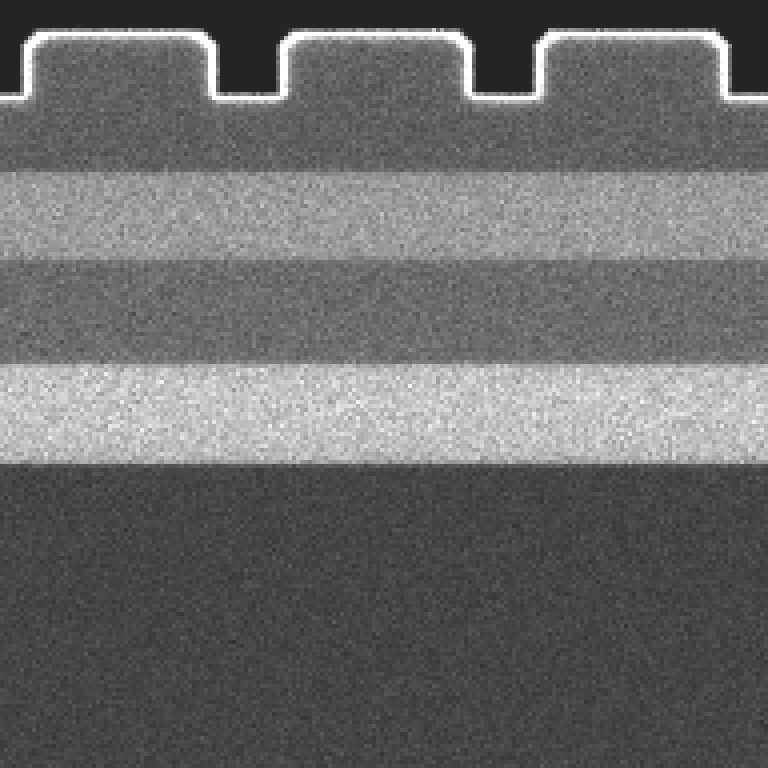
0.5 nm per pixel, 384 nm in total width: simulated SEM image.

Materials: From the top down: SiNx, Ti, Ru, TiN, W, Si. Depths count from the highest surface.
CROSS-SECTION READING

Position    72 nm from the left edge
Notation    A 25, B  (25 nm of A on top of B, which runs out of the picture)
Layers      Ti 70, Ru 44, TiN 52, W 50, Si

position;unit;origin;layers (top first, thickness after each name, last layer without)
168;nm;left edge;Ti 70, Ru 44, TiN 52, W 50, Si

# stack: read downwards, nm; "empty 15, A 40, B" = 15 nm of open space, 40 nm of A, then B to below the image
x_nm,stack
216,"Ti 70, Ru 44, TiN 52, W 50, Si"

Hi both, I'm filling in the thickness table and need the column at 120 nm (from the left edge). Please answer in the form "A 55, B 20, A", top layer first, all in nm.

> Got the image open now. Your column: empty 32, Ti 38, Ru 44, TiN 52, W 50, Si